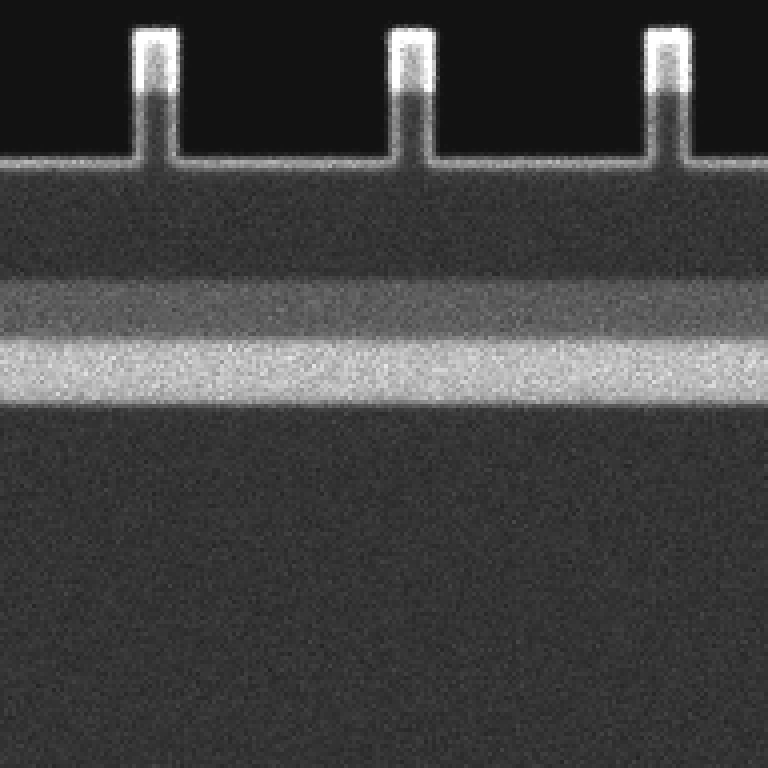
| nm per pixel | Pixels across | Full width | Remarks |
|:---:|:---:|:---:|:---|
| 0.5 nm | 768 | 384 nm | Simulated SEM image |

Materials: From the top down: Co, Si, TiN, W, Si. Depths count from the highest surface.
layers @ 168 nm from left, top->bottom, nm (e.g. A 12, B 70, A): empty 64, Si 60, TiN 30, W 32, Si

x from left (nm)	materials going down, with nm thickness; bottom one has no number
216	empty 64, Si 60, TiN 30, W 32, Si